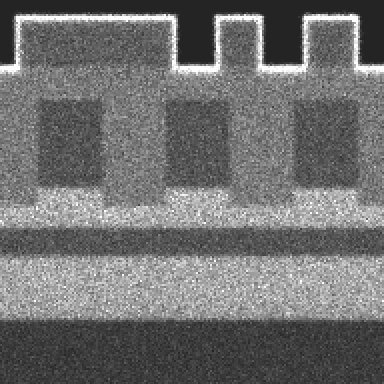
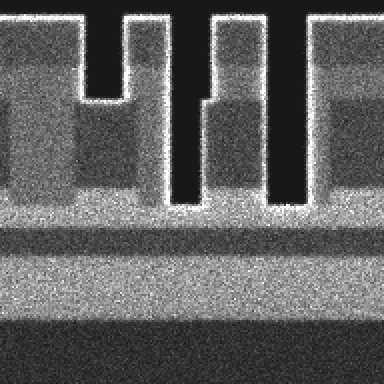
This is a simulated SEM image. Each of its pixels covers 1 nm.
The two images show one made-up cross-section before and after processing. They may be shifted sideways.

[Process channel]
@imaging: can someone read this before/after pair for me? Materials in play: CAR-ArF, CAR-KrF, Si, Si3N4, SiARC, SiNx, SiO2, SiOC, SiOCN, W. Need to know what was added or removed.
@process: SiO2 removed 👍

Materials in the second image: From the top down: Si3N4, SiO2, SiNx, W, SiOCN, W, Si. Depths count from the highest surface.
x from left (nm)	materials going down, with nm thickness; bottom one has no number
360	Si3N4 50, SiO2 34, SiNx 88, W 40, SiOCN 28, W 64, Si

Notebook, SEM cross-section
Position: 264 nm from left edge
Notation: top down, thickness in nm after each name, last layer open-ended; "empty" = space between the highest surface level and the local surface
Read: Si3N4 50, SiO2 34, SiNx 88, W 40, SiOCN 28, W 64, Si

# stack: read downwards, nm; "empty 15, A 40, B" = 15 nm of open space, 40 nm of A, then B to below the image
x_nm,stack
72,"Si3N4 50, SiO2 140, W 22, SiOCN 28, W 64, Si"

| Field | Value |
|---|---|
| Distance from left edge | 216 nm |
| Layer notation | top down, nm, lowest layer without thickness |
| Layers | Si3N4 50, SiO2 34, SiNx 88, W 40, SiOCN 28, W 64, Si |